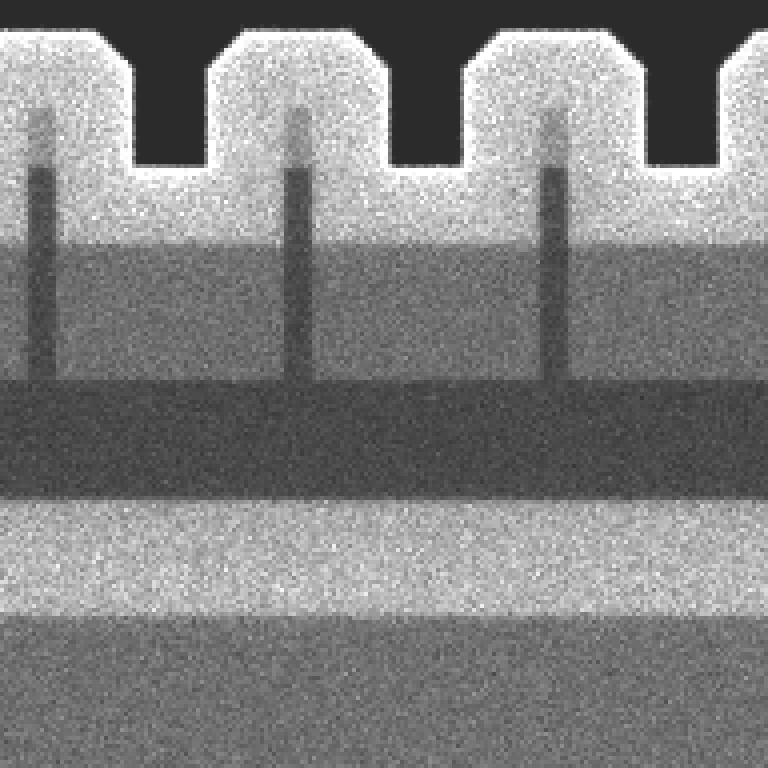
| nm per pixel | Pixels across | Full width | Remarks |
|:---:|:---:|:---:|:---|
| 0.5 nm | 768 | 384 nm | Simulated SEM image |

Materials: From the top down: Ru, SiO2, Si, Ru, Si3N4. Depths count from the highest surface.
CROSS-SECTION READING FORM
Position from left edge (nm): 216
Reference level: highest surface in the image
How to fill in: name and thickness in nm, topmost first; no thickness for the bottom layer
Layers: empty 68, Ru 38, Si3N4 68, Si 60, Ru 58, Si3N4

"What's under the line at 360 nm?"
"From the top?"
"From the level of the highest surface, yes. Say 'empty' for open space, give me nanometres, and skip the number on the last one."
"empty 18, Ru 88, Si3N4 68, Si 60, Ru 58, Si3N4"